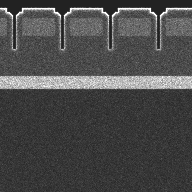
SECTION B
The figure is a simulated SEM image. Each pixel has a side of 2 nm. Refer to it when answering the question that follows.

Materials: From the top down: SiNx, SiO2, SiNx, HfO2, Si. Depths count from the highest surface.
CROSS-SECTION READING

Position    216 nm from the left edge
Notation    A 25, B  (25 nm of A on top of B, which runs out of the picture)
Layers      empty 14, SiNx 122, HfO2 26, Si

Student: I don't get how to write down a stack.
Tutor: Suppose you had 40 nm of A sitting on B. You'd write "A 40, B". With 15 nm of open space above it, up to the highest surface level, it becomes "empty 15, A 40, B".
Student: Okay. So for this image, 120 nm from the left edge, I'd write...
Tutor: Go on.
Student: empty 14, SiNx 122, HfO2 26, Si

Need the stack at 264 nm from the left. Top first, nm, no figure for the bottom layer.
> SiNx 20, SiO2 36, SiNx 80, HfO2 26, Si